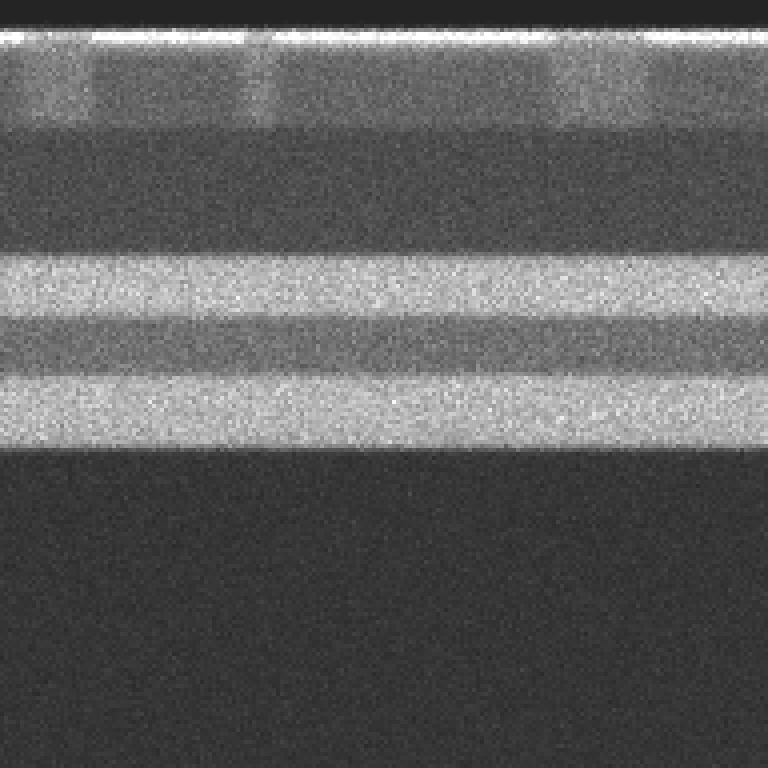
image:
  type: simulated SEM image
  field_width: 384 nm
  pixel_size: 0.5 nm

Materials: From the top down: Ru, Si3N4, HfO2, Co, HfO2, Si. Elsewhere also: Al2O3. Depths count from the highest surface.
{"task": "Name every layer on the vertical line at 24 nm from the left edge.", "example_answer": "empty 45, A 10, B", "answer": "Ru 48, Si3N4 64, HfO2 30, Co 30, HfO2 36, Si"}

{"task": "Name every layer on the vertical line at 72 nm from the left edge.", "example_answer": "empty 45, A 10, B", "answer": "Al2O3 48, Si3N4 64, HfO2 30, Co 30, HfO2 36, Si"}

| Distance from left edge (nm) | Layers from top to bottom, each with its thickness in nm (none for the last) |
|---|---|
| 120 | Al2O3 48, Si3N4 64, HfO2 30, Co 30, HfO2 36, Si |